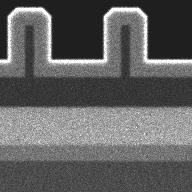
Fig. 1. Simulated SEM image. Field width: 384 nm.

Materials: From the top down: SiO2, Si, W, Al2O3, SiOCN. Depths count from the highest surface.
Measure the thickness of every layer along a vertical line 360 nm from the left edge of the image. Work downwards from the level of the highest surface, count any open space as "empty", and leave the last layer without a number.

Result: empty 104, SiO2 34, Si 60, W 76, Al2O3 32, SiOCN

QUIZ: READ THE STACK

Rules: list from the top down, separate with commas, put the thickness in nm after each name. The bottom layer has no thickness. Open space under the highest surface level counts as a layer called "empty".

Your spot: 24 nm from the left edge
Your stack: empty 8, SiO2 130, Si 60, W 76, Al2O3 32, SiOCN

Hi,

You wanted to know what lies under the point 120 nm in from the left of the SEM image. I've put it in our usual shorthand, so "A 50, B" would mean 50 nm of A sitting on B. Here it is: empty 104, SiO2 34, Si 60, W 76, Al2O3 32, SiOCN